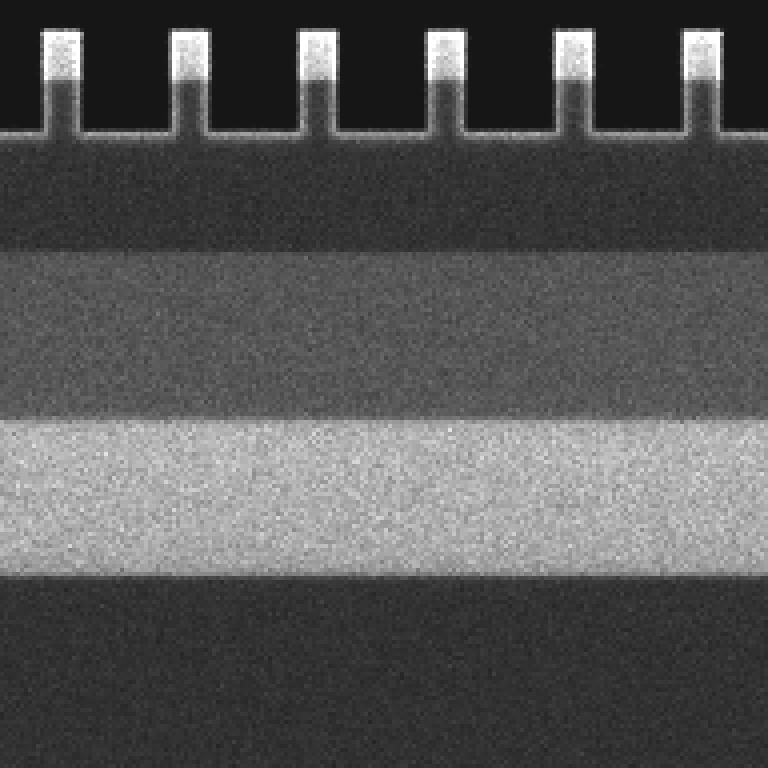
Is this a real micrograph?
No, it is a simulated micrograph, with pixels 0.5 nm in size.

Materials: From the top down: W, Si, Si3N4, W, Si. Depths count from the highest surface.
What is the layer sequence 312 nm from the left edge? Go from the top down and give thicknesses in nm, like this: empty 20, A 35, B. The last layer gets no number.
empty 50, Si 60, Si3N4 84, W 78, Si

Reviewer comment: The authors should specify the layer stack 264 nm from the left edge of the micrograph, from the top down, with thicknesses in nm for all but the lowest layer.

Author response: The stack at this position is empty 50, Si 60, Si3N4 84, W 78, Si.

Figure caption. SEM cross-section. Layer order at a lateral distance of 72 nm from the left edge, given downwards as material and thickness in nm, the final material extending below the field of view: empty 50, Si 60, Si3N4 84, W 78, Si